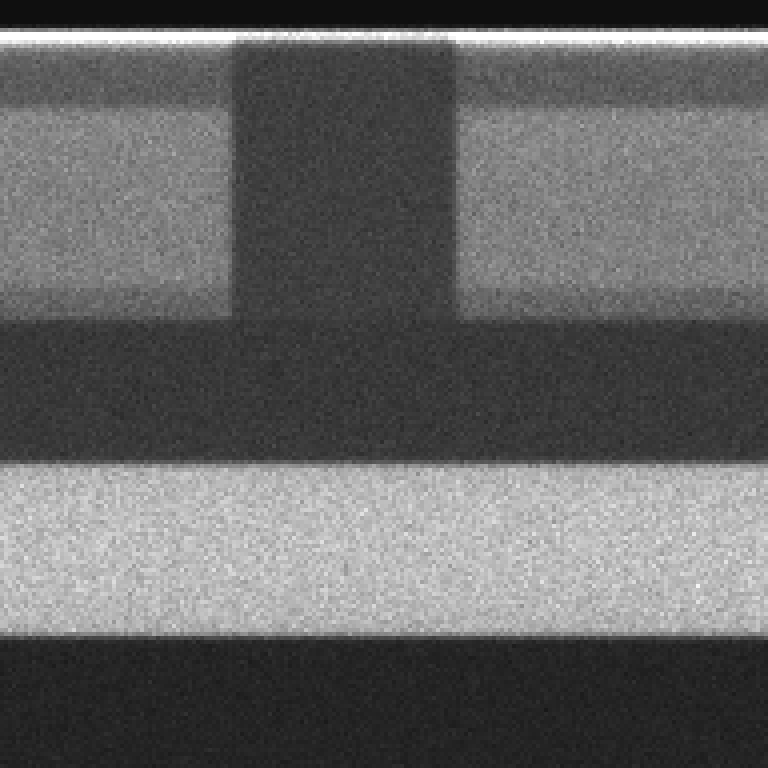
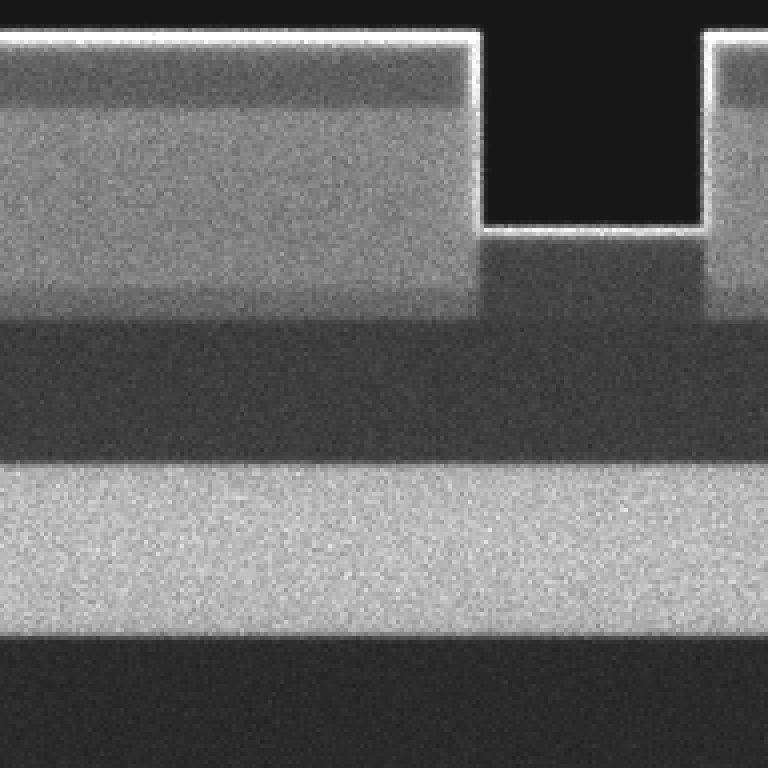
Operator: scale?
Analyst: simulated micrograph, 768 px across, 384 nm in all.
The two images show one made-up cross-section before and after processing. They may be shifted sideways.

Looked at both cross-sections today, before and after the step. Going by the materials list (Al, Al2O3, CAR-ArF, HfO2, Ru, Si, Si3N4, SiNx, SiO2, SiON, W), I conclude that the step removed Si3N4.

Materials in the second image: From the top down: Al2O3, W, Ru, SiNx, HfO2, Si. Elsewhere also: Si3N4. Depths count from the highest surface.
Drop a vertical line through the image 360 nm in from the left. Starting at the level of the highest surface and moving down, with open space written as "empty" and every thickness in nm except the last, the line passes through Al2O3 38, W 90, Ru 16, SiNx 72, HfO2 86, Si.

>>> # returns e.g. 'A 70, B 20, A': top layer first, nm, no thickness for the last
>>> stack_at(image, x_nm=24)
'Al2O3 38, W 90, Ru 16, SiNx 72, HfO2 86, Si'